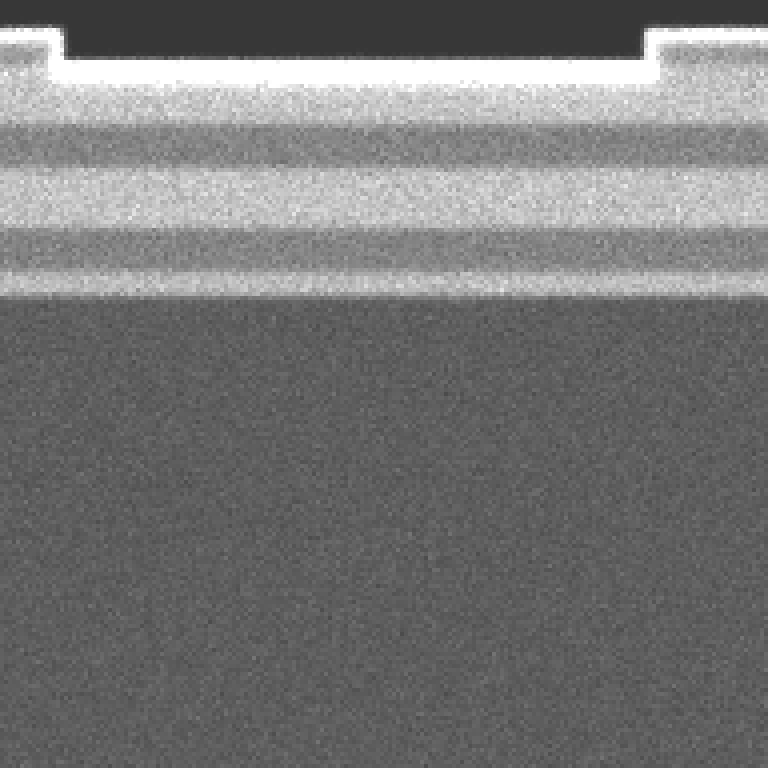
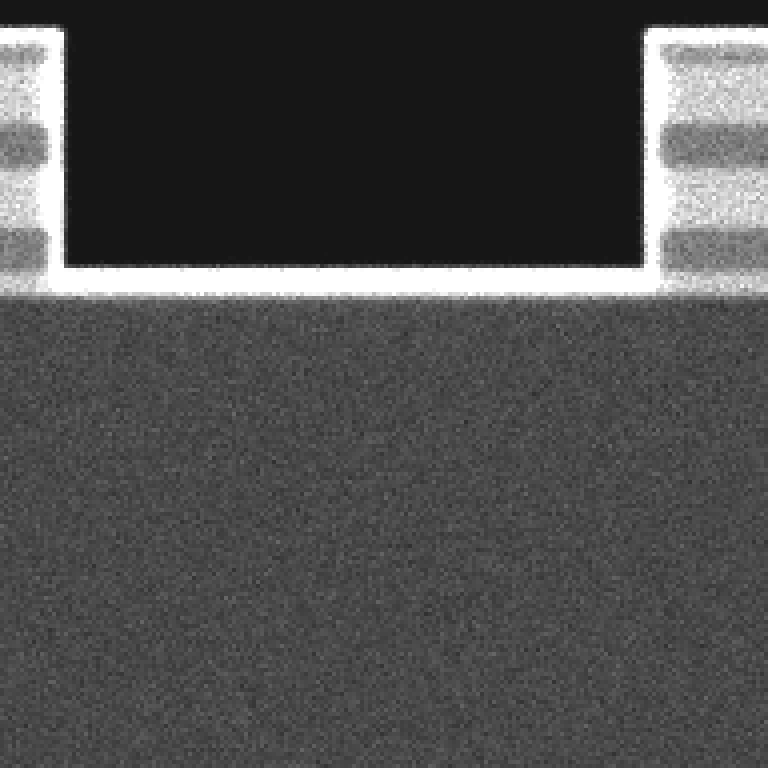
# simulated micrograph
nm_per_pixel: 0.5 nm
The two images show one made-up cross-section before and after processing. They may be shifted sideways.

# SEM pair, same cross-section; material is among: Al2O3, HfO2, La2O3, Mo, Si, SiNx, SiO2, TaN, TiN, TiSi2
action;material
removed;Al2O3 and SiNx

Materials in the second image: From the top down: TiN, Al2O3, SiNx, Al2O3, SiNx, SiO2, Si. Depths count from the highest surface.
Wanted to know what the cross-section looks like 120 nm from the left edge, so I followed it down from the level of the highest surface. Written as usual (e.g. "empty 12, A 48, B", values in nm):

empty 120, SiO2 12, Si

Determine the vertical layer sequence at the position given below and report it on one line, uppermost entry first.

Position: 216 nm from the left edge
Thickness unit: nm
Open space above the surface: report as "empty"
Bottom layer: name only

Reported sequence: empty 120, SiO2 12, Si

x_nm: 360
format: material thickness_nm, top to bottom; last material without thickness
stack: TiN 16, Al2O3 30, SiNx 22, Al2O3 30, SiNx 22, SiO2 12, Si